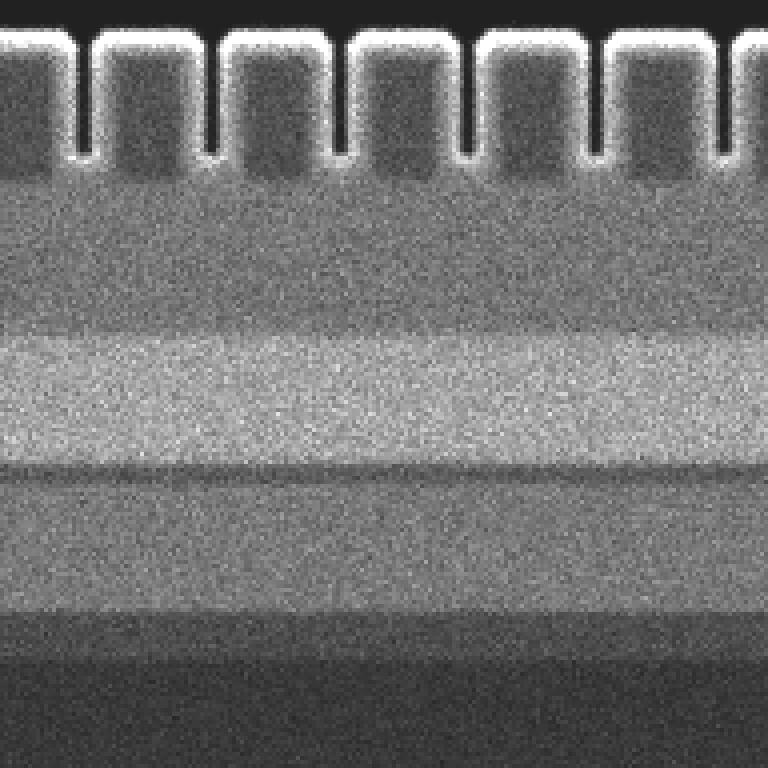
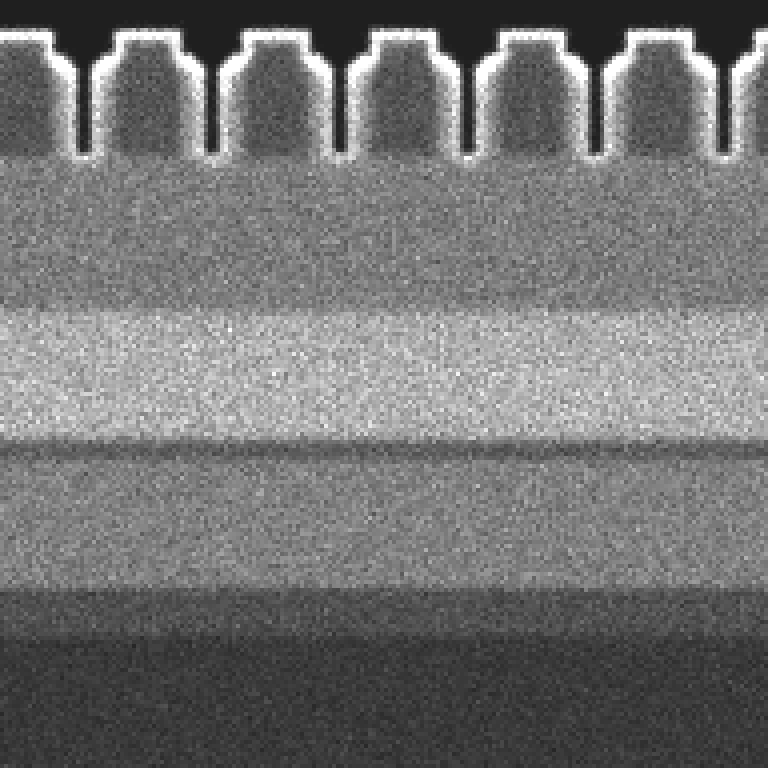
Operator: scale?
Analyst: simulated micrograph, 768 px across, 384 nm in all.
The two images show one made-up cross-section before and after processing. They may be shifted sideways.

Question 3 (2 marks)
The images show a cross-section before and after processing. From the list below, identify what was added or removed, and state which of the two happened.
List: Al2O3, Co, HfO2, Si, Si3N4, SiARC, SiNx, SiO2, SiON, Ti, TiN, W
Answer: SiO2 was removed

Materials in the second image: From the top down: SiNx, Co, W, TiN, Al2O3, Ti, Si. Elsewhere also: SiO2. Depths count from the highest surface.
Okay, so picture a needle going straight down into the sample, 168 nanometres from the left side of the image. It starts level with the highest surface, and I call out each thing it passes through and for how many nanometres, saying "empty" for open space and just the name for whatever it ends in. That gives empty 62, Co 78, W 64, TiN 10, Al2O3 64, Ti 24, Si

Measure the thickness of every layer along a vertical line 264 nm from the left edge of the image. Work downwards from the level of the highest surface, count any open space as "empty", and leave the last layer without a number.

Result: SiNx 62, Co 78, W 64, TiN 10, Al2O3 64, Ti 24, Si